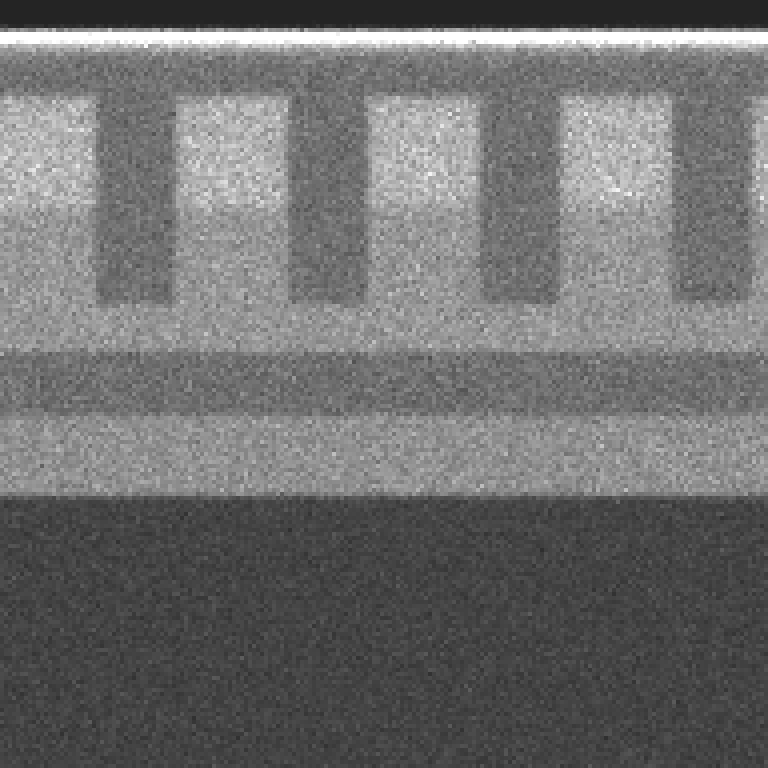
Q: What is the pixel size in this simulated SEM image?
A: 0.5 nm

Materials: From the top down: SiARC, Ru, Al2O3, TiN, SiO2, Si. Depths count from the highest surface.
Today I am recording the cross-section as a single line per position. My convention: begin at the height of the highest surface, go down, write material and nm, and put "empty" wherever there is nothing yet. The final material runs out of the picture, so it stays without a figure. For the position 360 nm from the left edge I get SiARC 136, Al2O3 24, TiN 32, SiO2 40, Si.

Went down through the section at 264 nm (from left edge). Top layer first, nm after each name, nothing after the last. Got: SiARC 136, Al2O3 24, TiN 32, SiO2 40, Si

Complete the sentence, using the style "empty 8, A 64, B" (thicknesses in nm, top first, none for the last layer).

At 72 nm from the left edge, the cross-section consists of SiARC 136, Al2O3 24, TiN 32, SiO2 40, Si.